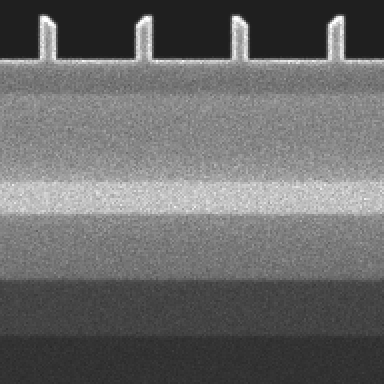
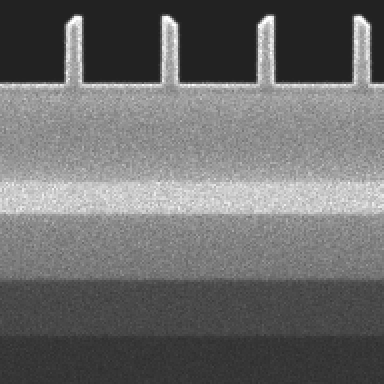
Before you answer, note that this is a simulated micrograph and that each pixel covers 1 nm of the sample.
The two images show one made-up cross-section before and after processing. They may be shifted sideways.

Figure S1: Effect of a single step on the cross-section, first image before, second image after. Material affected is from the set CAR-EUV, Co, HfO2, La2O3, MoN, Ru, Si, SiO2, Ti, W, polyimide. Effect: removed Co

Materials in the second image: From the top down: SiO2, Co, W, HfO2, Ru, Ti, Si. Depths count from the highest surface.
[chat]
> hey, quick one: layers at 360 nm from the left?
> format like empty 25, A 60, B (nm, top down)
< SiO2 44, Co 34, W 88, HfO2 32, Ru 66, Ti 56, Si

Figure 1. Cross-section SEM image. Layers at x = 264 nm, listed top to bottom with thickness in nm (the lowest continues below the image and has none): empty 2, SiO2 42, Co 34, W 88, HfO2 32, Ru 66, Ti 56, Si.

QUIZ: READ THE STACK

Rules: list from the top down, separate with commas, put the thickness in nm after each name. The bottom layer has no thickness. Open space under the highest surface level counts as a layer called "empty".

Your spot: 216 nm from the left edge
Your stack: empty 68, Co 10, W 88, HfO2 32, Ru 66, Ti 56, Si